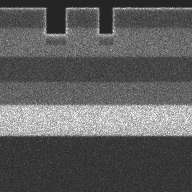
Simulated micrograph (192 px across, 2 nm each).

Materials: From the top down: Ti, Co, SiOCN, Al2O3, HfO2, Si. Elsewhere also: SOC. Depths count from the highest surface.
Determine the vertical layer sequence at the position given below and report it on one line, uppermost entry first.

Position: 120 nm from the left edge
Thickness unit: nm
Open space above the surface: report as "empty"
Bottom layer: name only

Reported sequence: empty 52, SOC 22, Co 24, SiOCN 50, Al2O3 46, HfO2 62, Si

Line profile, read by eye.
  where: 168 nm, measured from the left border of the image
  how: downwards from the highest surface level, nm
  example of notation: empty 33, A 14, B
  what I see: Ti 40, Co 58, SiOCN 50, Al2O3 46, HfO2 62, Si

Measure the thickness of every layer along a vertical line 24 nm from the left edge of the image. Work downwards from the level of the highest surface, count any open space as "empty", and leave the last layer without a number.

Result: Ti 40, Co 58, SiOCN 50, Al2O3 46, HfO2 62, Si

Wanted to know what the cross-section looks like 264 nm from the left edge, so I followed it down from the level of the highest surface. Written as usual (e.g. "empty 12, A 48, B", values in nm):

Ti 40, Co 58, SiOCN 50, Al2O3 46, HfO2 62, Si